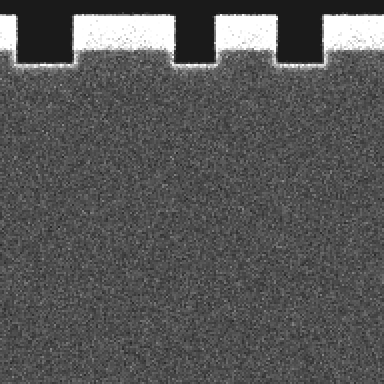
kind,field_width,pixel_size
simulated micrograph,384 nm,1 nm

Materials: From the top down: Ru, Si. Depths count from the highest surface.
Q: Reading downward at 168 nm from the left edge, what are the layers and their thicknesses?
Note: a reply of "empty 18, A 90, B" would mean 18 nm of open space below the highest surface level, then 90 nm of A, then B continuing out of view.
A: Ru 34, Si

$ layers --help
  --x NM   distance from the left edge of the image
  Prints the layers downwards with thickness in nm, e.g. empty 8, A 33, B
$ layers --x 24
empty 48, Si